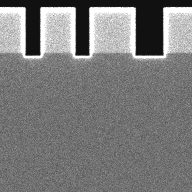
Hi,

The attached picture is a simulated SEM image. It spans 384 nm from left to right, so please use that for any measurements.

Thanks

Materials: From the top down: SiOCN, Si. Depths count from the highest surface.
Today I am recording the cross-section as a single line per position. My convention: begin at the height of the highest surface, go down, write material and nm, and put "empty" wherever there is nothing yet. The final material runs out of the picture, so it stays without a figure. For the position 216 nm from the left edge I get SiOCN 90, Si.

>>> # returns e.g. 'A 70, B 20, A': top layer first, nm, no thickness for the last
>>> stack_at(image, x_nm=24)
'SiOCN 90, Si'